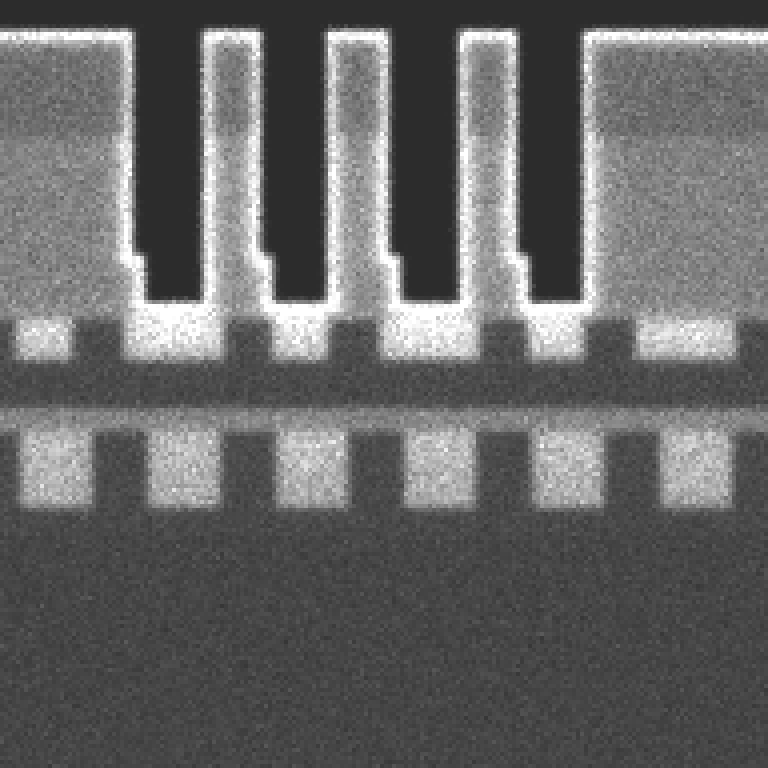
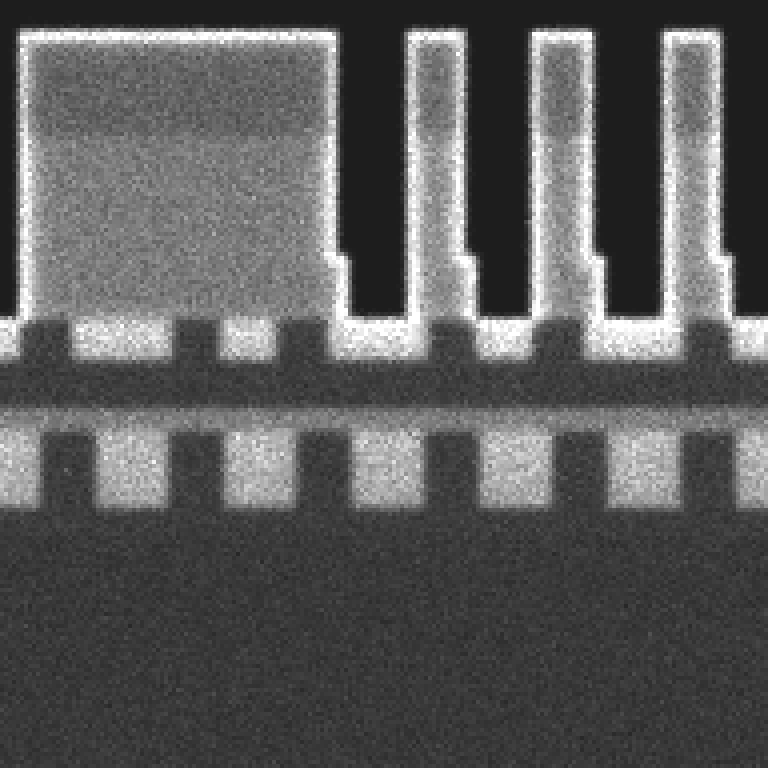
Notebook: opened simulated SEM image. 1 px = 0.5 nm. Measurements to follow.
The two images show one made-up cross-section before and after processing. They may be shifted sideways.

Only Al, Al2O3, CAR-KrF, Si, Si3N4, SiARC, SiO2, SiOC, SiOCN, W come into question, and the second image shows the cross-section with Al2O3 removed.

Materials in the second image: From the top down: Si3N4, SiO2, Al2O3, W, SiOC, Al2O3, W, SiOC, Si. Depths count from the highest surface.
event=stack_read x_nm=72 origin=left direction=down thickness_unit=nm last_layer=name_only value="Si3N4 52, SiO2 84, Al2O3 8, W 20, SiOC 24, Al2O3 12, W 38, SiOC 14, Si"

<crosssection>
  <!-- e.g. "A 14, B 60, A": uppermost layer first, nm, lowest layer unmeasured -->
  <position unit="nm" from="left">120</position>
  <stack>Si3N4 52, SiO2 84, Al2O3 8, W 20, SiOC 24, Al2O3 12, W 38, SiOC 14, Si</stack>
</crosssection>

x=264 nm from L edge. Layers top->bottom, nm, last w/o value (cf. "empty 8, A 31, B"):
empty 144, W 20, SiOC 24, Al2O3 12, W 38, SiOC 14, Si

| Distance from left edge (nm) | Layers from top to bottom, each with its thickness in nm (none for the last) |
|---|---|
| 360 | empty 112, SiO2 24, Al2O3 8, SiOC 44, Al2O3 12, SiOC 52, Si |